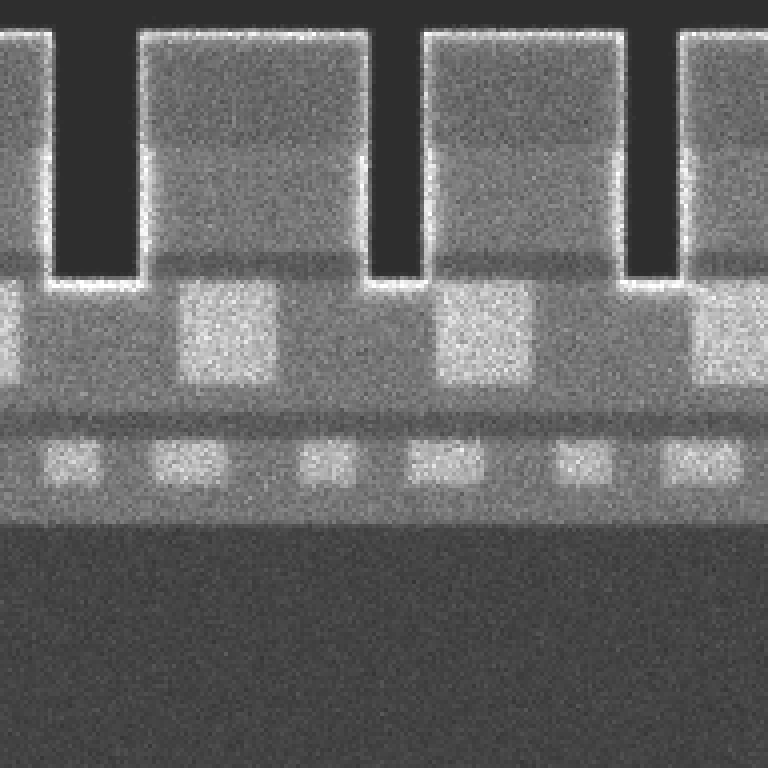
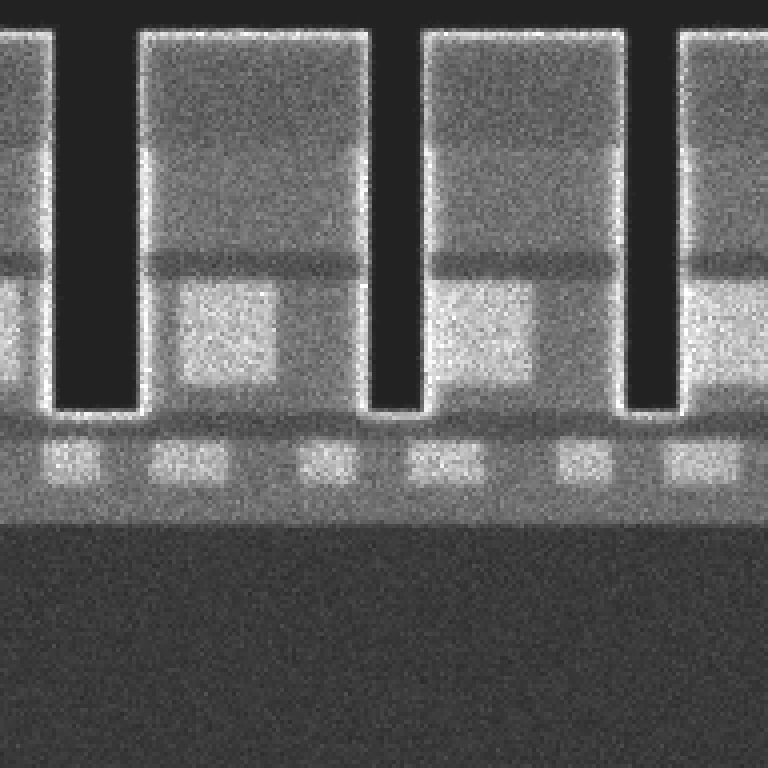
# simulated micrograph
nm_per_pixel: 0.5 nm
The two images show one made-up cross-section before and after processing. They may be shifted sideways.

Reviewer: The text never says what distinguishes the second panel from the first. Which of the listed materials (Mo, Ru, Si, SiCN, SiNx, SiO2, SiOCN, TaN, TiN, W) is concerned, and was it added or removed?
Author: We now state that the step removed SiO2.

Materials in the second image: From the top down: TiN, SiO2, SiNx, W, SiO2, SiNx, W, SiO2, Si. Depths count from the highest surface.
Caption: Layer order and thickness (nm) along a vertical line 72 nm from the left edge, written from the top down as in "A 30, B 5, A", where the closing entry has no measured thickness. TiN 58, SiO2 52, SiNx 14, SiO2 66, SiNx 14, SiO2 42, Si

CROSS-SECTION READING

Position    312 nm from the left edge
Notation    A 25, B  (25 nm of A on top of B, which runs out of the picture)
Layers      empty 190, SiNx 14, SiO2 42, Si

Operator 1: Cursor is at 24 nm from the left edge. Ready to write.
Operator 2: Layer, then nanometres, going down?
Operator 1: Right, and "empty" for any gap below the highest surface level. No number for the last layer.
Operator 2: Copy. TiN 58, SiO2 52, SiNx 14, SiO2 66, SiNx 14, W 22, SiO2 20, Si